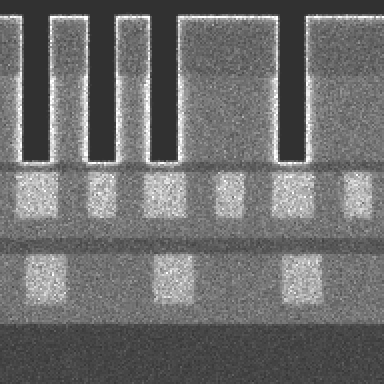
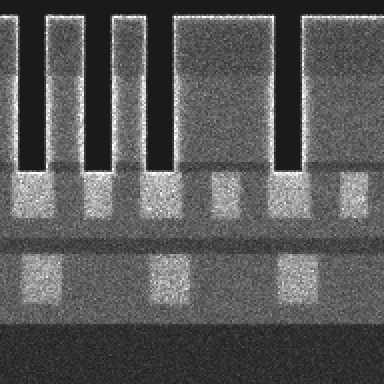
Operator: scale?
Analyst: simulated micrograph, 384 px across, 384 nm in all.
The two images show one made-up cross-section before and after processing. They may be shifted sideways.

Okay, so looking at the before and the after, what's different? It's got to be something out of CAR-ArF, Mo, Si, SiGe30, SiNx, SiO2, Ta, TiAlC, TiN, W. SiNx, removed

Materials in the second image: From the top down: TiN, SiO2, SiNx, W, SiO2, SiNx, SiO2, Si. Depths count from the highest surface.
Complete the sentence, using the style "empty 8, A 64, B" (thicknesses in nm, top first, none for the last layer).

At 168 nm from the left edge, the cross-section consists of empty 156, W 46, SiO2 20, SiNx 16, W 50, SiO2 20, Si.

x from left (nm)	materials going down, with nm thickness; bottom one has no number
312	TiN 60, SiO2 86, SiNx 10, SiO2 66, SiNx 16, W 50, SiO2 20, Si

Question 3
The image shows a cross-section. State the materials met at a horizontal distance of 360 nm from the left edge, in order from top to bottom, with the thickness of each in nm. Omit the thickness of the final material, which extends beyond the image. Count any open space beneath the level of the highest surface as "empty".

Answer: TiN 60, SiO2 86, SiNx 10, W 46, SiO2 20, SiNx 16, SiO2 70, Si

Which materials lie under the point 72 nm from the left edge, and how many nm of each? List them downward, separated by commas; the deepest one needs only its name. TiN 60, SiO2 86, SiNx 10, SiO2 66, SiNx 16, SiO2 70, Si